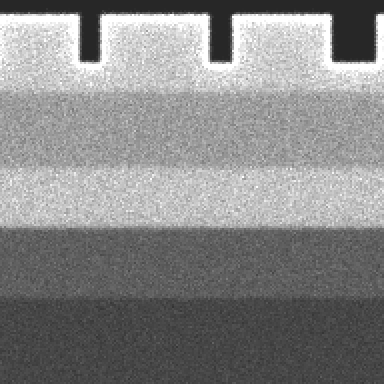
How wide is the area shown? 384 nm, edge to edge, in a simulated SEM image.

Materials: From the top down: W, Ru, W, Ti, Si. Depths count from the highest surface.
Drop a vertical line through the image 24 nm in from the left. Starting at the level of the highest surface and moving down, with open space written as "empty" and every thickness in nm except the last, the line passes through W 76, Ru 76, W 60, Ti 70, Si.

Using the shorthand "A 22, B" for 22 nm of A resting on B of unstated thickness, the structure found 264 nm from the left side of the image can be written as W 76, Ru 76, W 60, Ti 70, Si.